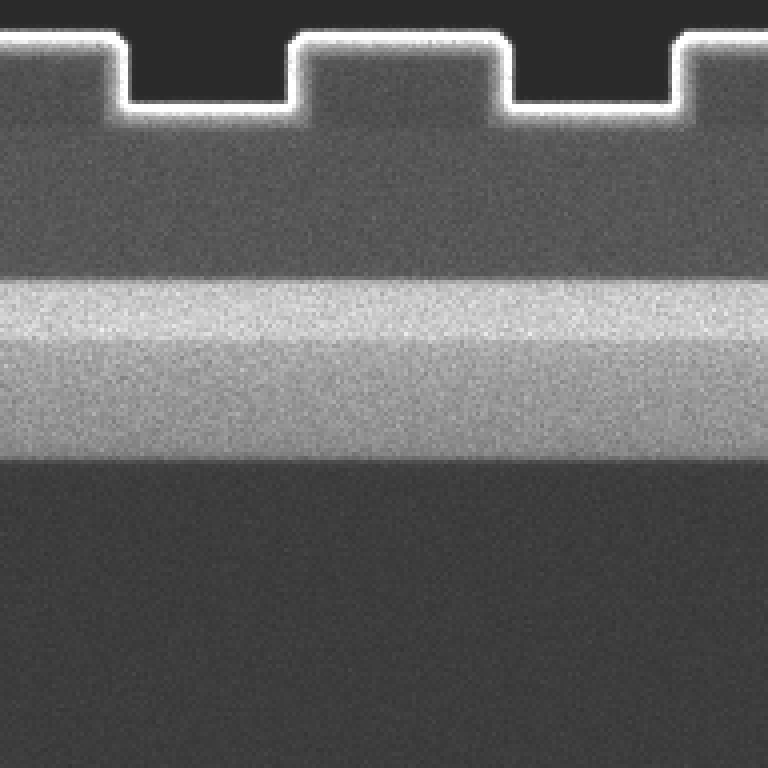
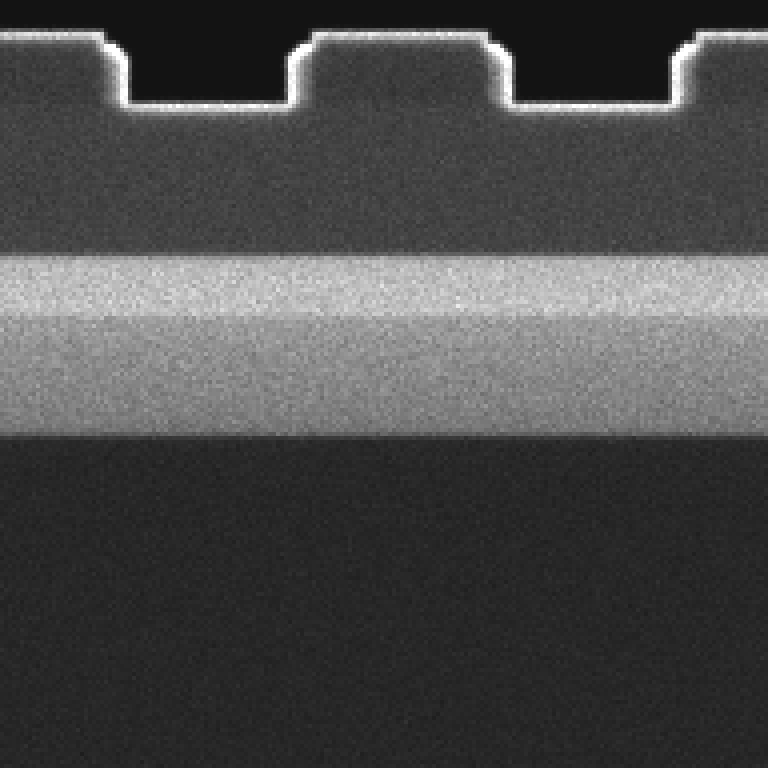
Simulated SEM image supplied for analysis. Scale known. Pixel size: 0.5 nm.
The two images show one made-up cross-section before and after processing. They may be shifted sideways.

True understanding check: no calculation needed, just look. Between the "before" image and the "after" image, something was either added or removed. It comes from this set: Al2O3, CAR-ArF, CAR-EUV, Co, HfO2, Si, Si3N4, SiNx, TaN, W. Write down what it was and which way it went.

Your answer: Al2O3 (removed)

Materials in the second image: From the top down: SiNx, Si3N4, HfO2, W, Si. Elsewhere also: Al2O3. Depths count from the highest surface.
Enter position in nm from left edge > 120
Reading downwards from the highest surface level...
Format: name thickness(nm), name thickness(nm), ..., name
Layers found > empty 36, Si3N4 76, HfO2 30, W 60, Si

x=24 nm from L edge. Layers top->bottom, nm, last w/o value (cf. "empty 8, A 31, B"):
SiNx 36, Si3N4 76, HfO2 30, W 60, Si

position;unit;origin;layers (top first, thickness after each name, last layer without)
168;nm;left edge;SiNx 36, Si3N4 76, HfO2 30, W 60, Si